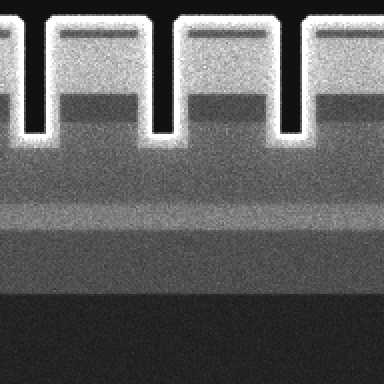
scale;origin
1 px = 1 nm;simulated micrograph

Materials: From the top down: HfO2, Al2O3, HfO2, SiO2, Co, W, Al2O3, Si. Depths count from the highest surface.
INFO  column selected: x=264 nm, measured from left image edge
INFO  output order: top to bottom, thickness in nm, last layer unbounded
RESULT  HfO2 14, Al2O3 8, HfO2 56, SiO2 28, Co 82, W 26, Al2O3 64, Si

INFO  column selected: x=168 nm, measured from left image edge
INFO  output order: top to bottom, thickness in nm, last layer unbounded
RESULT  empty 118, HfO2 14, Co 56, W 26, Al2O3 64, Si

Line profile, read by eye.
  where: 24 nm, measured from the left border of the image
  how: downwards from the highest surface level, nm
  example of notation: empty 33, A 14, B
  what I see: empty 118, HfO2 14, Co 56, W 26, Al2O3 64, Si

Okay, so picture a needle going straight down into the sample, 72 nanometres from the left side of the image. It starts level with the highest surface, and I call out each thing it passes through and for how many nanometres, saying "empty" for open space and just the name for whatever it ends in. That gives HfO2 14, Al2O3 8, HfO2 56, SiO2 28, Co 82, W 26, Al2O3 64, Si